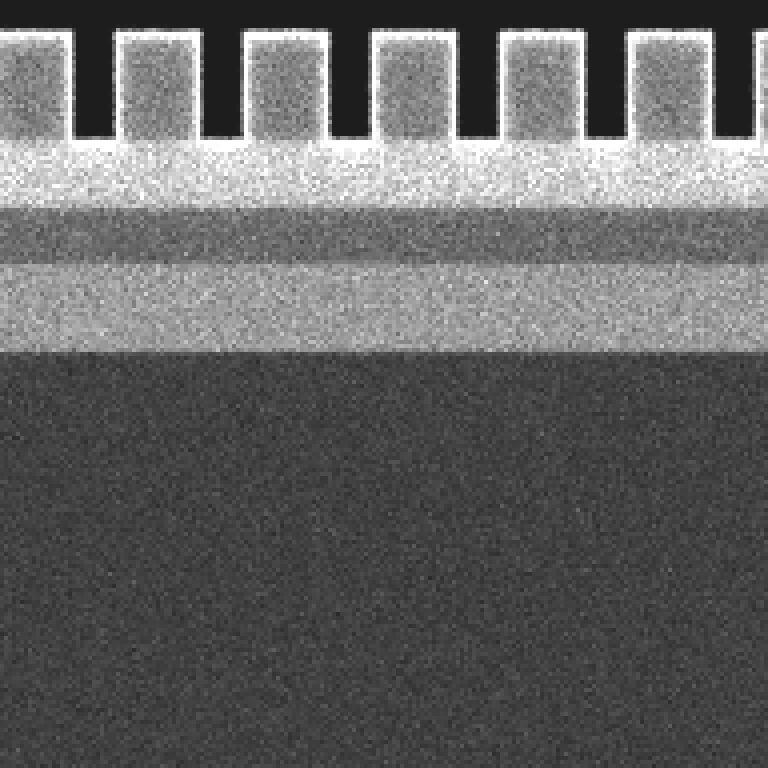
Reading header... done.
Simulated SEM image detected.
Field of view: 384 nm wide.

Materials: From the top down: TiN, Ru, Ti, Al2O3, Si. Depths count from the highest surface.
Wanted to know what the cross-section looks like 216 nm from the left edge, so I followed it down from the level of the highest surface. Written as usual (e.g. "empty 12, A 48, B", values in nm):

TiN 54, Ru 34, Ti 28, Al2O3 44, Si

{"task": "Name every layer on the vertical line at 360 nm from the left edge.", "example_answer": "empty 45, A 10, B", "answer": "empty 54, Ru 34, Ti 28, Al2O3 44, Si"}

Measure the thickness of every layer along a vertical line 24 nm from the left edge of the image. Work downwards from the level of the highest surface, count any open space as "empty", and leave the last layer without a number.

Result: TiN 54, Ru 34, Ti 28, Al2O3 44, Si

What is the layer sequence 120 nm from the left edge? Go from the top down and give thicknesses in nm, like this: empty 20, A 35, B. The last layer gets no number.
empty 54, Ru 34, Ti 28, Al2O3 44, Si